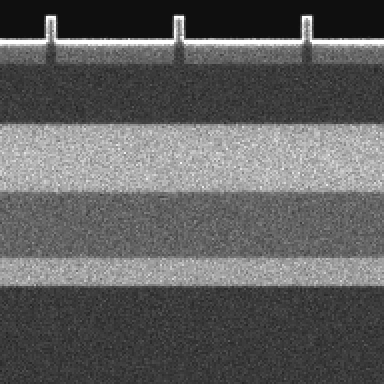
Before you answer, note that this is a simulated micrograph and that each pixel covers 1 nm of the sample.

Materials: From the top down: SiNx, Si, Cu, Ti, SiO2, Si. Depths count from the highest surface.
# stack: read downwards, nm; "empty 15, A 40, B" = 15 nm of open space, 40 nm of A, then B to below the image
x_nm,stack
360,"empty 24, SiNx 24, Si 60, Cu 68, Ti 66, SiO2 28, Si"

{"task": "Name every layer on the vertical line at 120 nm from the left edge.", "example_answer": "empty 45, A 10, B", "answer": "empty 24, SiNx 24, Si 60, Cu 68, Ti 66, SiO2 28, Si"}